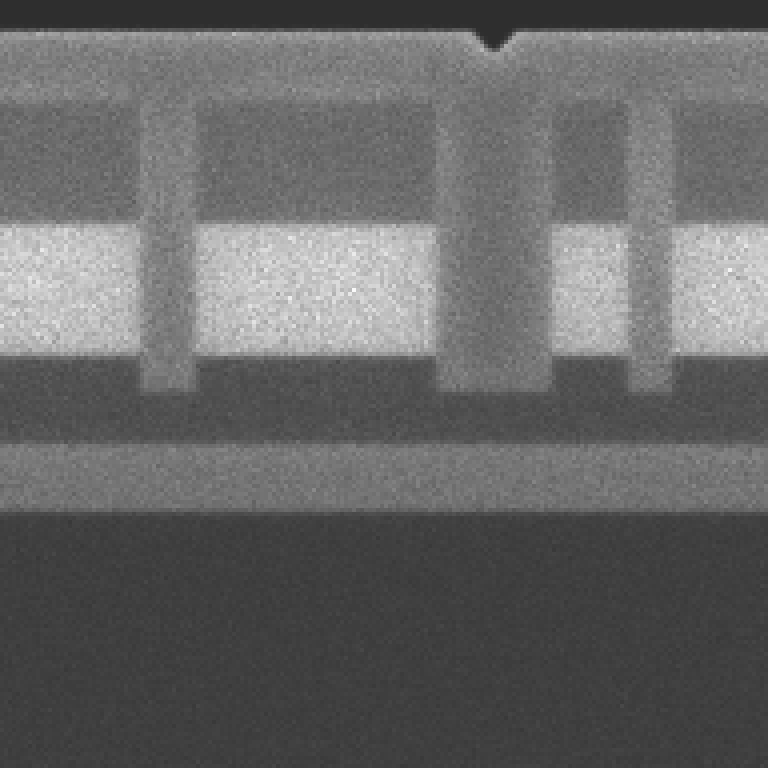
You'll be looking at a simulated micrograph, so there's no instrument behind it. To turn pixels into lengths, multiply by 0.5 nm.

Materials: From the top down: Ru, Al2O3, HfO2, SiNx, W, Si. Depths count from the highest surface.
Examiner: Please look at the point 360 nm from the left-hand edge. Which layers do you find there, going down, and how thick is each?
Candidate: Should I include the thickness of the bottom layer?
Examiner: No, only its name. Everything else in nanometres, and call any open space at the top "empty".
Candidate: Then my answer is Ru 34, Al2O3 62, HfO2 66, SiNx 44, W 34, Si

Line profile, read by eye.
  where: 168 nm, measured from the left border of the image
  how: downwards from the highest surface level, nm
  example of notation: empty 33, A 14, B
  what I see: Ru 34, Al2O3 62, HfO2 66, SiNx 44, W 34, Si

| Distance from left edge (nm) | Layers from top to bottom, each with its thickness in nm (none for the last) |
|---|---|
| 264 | Ru 180, SiNx 26, W 34, Si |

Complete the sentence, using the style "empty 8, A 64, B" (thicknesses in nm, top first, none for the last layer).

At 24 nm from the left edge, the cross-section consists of Ru 34, Al2O3 62, HfO2 66, SiNx 44, W 34, Si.